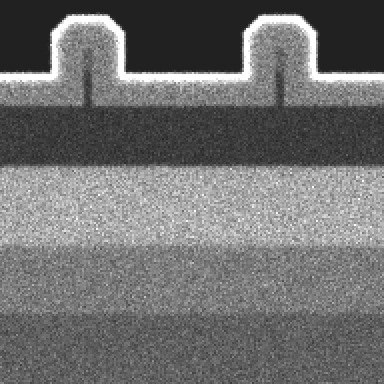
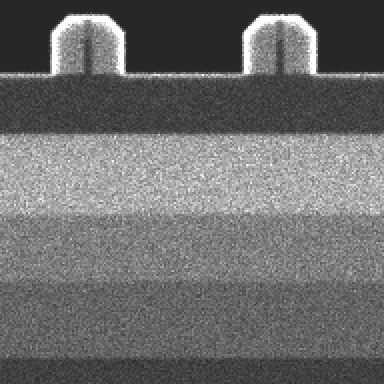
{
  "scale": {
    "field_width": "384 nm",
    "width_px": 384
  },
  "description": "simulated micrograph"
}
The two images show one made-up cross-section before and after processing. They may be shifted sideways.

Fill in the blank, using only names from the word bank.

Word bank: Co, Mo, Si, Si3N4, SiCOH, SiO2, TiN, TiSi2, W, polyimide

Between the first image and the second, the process removed SiO2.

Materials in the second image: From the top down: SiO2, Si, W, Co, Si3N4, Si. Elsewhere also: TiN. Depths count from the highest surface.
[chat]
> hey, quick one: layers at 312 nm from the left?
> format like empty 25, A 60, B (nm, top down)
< empty 14, SiO2 44, Si 60, W 80, Co 68, Si3N4 76, Si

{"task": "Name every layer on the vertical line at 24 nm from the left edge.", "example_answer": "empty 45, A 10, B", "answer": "empty 58, Si 60, W 80, Co 68, Si3N4 76, Si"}